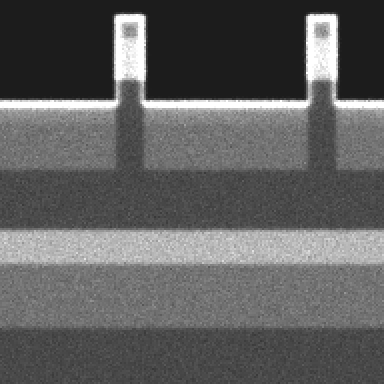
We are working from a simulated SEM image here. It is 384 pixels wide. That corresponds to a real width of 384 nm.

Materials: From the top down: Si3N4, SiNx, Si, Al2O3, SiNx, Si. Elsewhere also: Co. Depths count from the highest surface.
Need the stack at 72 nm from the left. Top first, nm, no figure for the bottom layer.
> empty 86, Si3N4 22, SiNx 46, Si 60, Al2O3 34, SiNx 64, Si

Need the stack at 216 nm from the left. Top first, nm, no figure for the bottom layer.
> empty 86, Si3N4 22, SiNx 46, Si 60, Al2O3 34, SiNx 64, Si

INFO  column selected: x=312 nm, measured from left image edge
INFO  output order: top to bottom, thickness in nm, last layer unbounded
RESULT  Si3N4 22, Co 42, Si 150, Al2O3 34, SiNx 64, Si